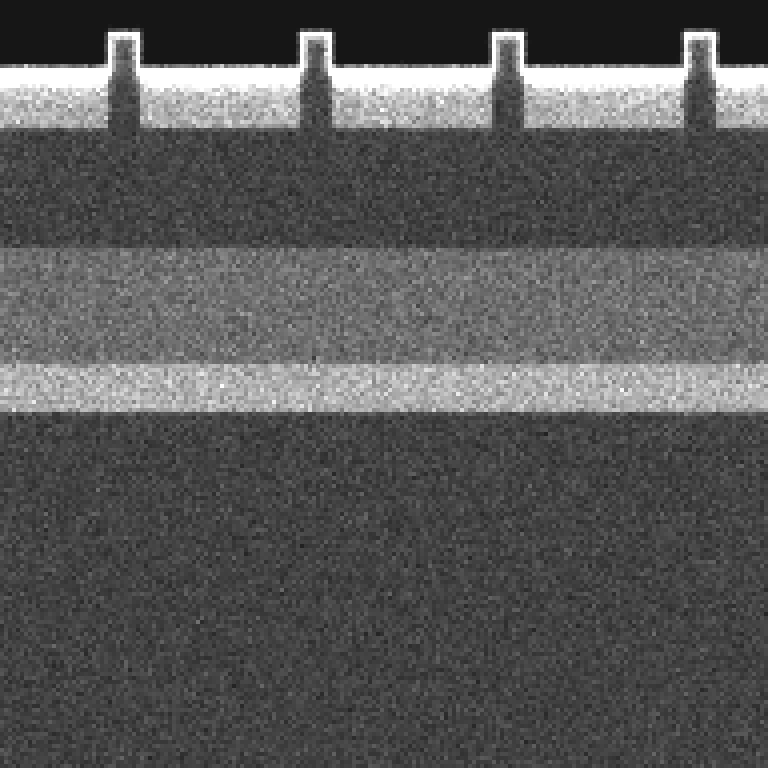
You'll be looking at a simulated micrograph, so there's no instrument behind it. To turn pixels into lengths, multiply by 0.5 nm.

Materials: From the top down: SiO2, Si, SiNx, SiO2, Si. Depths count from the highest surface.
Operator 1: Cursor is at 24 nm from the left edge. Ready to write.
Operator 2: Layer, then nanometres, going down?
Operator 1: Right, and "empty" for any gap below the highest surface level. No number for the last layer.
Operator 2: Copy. empty 18, SiO2 30, Si 60, SiNx 58, SiO2 24, Si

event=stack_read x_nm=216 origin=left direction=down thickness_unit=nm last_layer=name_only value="empty 18, SiO2 30, Si 60, SiNx 58, SiO2 24, Si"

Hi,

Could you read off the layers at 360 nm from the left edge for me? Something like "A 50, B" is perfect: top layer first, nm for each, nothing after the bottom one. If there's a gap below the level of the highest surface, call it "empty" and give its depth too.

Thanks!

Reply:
empty 18, SiO2 30, Si 60, SiNx 58, SiO2 24, Si